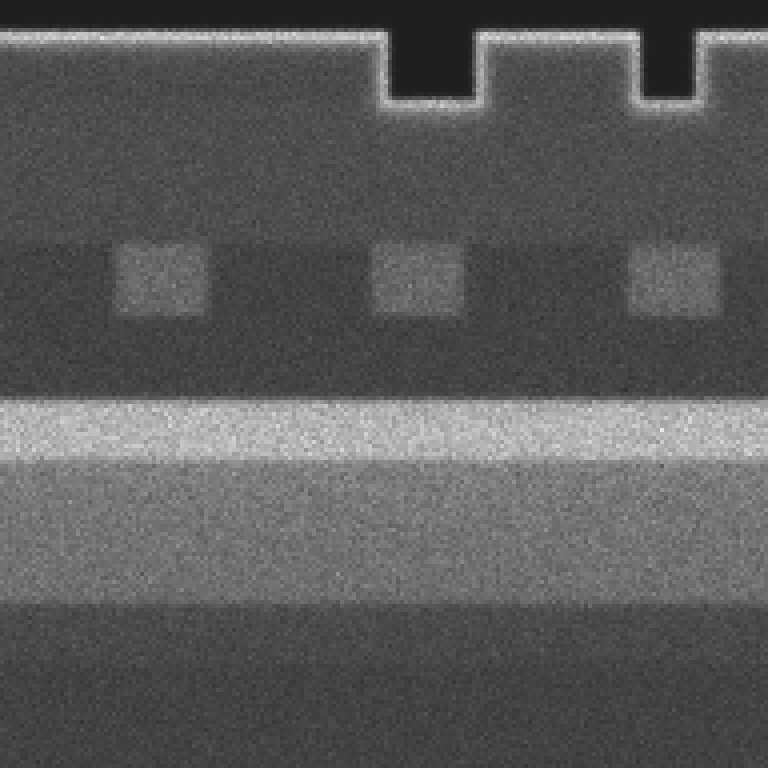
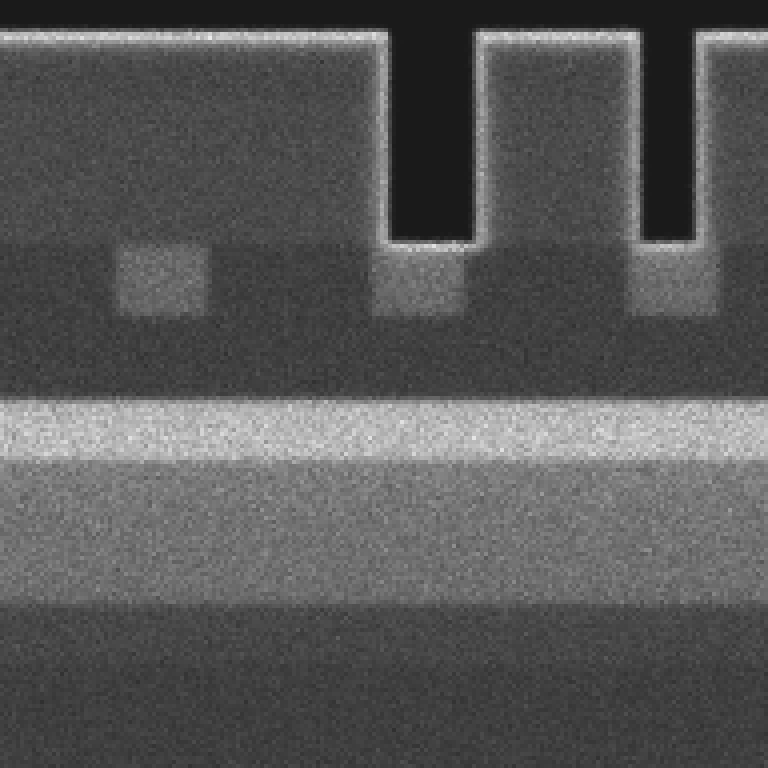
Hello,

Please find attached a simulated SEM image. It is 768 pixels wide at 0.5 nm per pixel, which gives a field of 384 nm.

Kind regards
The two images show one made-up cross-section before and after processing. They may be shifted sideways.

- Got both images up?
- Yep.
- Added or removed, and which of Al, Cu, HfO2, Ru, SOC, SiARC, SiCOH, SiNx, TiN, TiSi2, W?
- removed, SOC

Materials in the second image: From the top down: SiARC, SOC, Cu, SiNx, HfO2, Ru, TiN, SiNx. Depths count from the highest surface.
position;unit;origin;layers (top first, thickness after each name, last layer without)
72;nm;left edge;SiARC 34, SOC 72, Cu 36, SiNx 42, HfO2 30, Ru 72, TiN 30, SiNx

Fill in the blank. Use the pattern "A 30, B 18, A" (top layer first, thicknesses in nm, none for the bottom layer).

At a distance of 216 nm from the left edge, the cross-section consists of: empty 106, Cu 36, SiNx 42, HfO2 30, Ru 72, TiN 30, SiNx